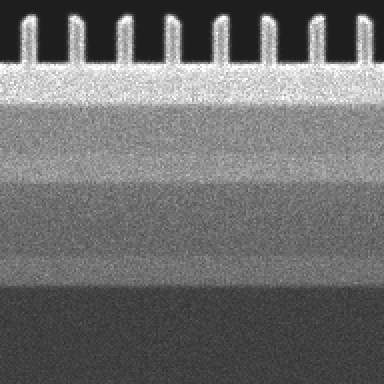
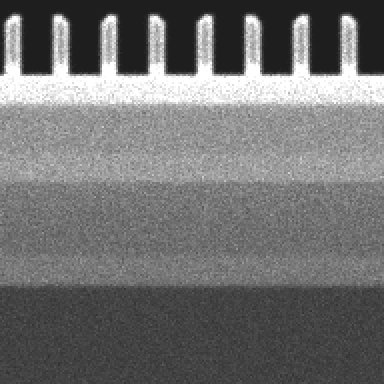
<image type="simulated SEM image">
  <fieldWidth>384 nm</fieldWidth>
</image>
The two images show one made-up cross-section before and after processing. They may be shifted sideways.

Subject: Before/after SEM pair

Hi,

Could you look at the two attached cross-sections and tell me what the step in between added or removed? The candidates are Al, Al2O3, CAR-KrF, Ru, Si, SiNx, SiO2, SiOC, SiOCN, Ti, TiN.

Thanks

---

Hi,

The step removed Ru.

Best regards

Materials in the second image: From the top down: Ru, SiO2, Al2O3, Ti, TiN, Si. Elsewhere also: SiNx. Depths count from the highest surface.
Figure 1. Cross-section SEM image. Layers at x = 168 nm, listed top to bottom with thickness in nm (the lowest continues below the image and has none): empty 60, Ru 28, SiO2 50, Al2O3 28, Ti 74, TiN 30, Si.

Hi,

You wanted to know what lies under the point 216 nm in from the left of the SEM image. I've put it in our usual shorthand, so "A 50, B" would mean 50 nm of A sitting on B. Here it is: empty 60, Ru 28, SiO2 50, Al2O3 28, Ti 74, TiN 30, Si